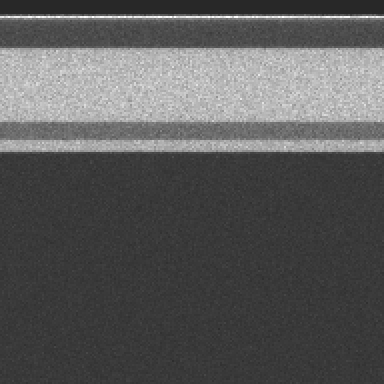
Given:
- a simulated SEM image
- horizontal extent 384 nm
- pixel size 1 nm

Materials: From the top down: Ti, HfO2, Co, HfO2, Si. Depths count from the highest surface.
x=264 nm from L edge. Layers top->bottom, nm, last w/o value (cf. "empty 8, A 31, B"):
Ti 32, HfO2 74, Co 18, HfO2 12, Si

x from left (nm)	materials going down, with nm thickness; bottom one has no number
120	Ti 32, HfO2 74, Co 18, HfO2 12, Si